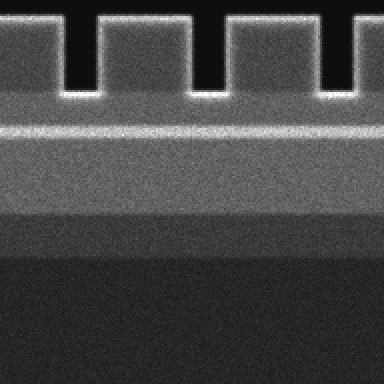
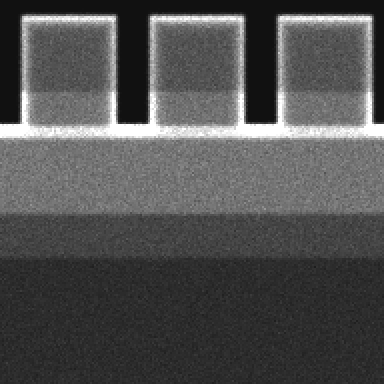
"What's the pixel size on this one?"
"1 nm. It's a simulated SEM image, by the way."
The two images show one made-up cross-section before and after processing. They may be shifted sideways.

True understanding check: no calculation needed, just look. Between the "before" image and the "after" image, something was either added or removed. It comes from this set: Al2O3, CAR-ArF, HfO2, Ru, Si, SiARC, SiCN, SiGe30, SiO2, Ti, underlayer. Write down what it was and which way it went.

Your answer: SiO2 (removed)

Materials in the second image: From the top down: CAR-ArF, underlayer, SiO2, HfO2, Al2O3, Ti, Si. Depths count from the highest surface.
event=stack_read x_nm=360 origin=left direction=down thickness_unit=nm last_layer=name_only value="CAR-ArF 46, underlayer 30, SiO2 34, HfO2 12, Al2O3 76, Ti 44, Si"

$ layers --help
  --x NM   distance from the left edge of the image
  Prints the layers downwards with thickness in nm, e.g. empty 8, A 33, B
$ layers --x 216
CAR-ArF 46, underlayer 30, SiO2 34, HfO2 12, Al2O3 76, Ti 44, Si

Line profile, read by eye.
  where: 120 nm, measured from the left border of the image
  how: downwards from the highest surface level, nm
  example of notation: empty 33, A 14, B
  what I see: empty 110, HfO2 12, Al2O3 76, Ti 44, Si